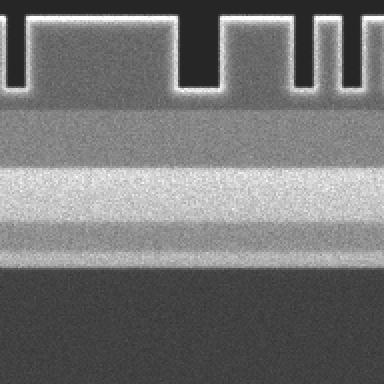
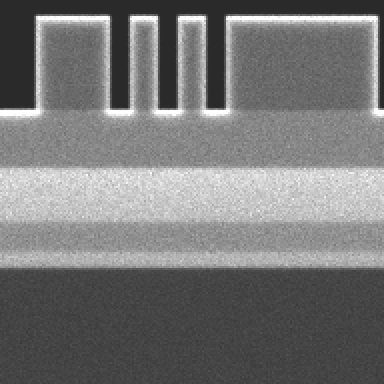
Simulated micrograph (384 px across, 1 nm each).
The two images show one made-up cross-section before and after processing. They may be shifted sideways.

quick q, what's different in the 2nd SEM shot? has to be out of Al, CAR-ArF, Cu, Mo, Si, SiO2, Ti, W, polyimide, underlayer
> underlayer removed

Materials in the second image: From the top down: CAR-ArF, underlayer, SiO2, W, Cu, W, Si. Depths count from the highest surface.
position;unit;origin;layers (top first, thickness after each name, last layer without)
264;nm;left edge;CAR-ArF 72, underlayer 22, SiO2 58, W 54, Cu 30, W 16, Si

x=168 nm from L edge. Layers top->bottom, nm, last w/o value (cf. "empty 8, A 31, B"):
empty 94, SiO2 58, W 54, Cu 30, W 16, Si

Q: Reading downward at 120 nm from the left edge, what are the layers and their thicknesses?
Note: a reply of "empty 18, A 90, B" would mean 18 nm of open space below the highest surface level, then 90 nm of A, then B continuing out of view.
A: empty 94, SiO2 58, W 54, Cu 30, W 16, Si